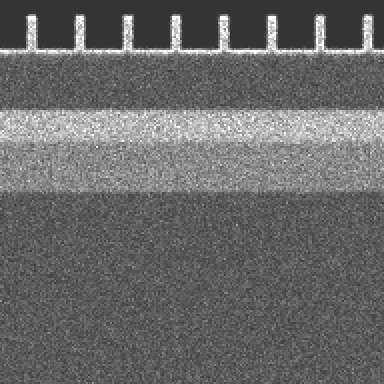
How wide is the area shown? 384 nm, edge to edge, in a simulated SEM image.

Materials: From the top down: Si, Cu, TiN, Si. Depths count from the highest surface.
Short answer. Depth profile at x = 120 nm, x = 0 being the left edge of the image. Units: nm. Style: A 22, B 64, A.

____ empty 34, Si 60, Cu 32, TiN 50, Si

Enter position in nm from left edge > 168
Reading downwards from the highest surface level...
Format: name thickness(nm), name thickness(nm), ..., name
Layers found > empty 34, Si 60, Cu 32, TiN 50, Si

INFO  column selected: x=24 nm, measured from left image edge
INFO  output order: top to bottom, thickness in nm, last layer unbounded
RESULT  empty 34, Si 60, Cu 32, TiN 50, Si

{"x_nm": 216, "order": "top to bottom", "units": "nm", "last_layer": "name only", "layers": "empty 34, Si 60, Cu 32, TiN 50, Si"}